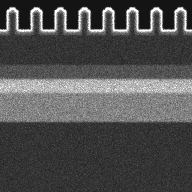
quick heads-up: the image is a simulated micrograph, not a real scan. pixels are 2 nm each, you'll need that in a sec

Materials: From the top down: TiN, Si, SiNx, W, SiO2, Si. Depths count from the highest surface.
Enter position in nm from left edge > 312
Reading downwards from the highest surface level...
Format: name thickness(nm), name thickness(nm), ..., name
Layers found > TiN 10, Si 104, SiNx 28, W 28, SiO2 58, Si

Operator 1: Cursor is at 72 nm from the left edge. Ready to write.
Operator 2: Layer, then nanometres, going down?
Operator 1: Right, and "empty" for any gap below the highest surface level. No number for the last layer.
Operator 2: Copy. TiN 10, Si 104, SiNx 28, W 28, SiO2 58, Si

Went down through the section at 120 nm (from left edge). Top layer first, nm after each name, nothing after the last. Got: TiN 10, Si 104, SiNx 28, W 28, SiO2 58, Si